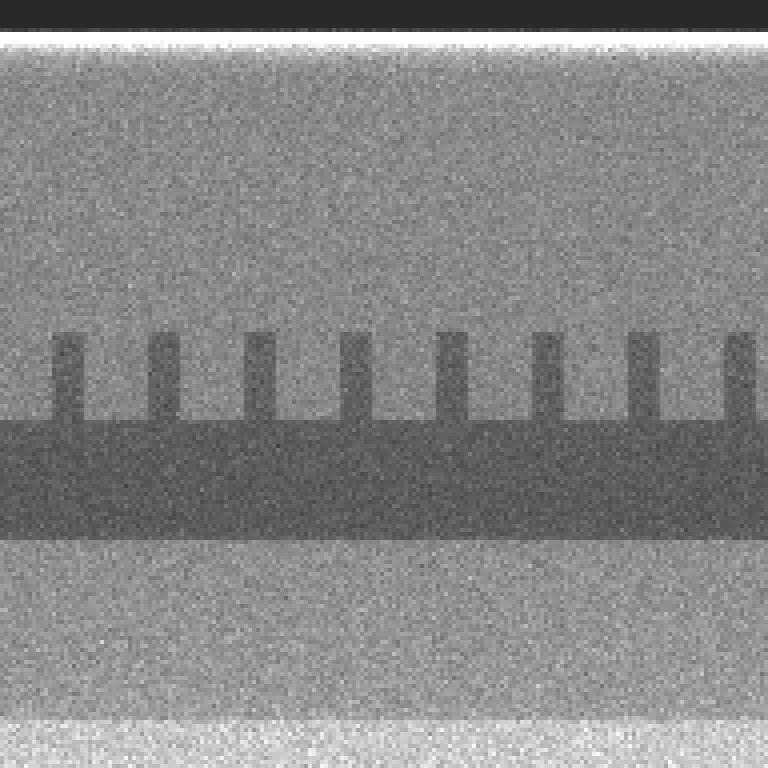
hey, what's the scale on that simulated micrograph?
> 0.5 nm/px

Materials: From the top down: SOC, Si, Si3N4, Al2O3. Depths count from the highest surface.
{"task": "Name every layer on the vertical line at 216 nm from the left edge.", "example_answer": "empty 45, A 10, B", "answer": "SOC 194, Si 60, Si3N4 90, Al2O3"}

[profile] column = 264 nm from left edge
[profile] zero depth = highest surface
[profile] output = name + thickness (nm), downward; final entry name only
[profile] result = SOC 194, Si 60, Si3N4 90, Al2O3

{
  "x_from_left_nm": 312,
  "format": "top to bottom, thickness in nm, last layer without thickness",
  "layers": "SOC 194, Si 60, Si3N4 90, Al2O3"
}